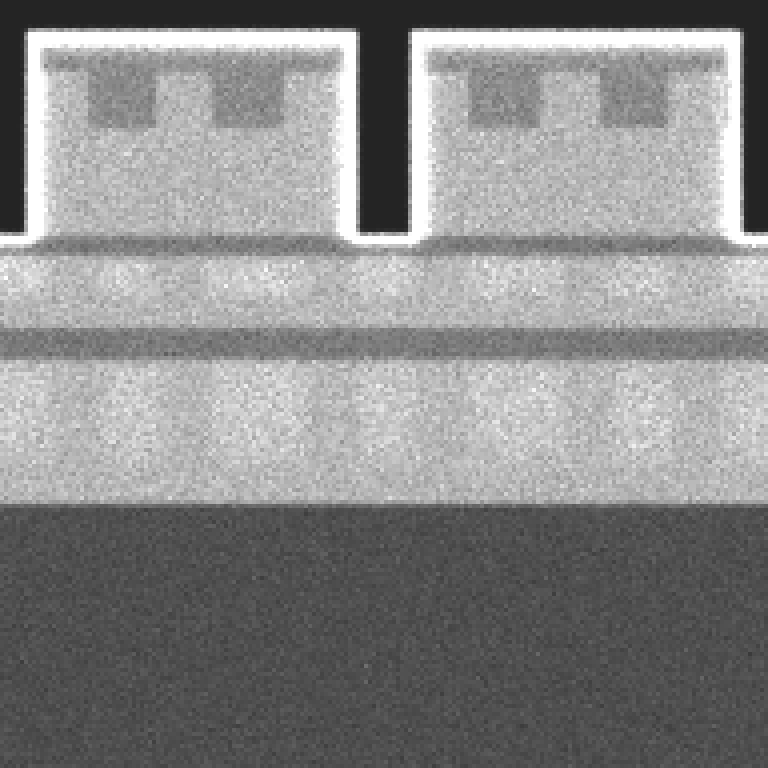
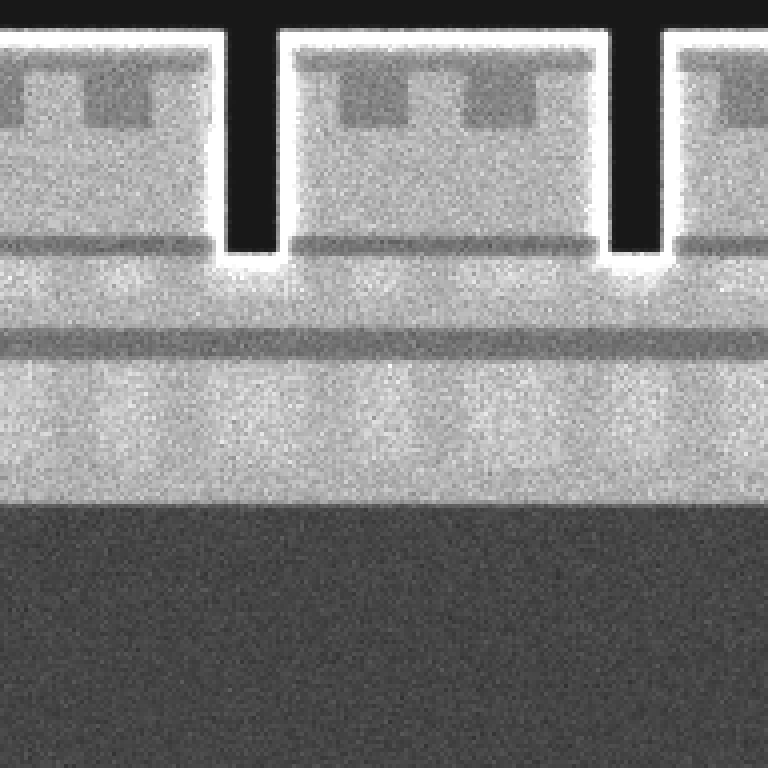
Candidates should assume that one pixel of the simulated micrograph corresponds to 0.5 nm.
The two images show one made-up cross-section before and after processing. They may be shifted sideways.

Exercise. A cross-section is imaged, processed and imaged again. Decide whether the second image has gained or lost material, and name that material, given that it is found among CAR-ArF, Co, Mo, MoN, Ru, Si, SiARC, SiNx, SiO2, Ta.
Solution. removed: SiNx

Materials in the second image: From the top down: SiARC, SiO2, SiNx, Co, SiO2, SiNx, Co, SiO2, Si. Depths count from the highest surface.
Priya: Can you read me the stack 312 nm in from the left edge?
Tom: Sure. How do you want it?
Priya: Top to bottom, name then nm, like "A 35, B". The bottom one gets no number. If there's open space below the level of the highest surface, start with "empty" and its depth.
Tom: empty 112, Co 20, SiO2 16, SiNx 16, Co 52, SiO2 20, Si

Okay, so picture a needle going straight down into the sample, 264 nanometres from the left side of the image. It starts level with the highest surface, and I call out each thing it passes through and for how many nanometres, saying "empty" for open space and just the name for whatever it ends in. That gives SiARC 48, SiO2 54, SiNx 10, Co 20, SiO2 16, SiNx 16, Co 52, SiO2 20, Si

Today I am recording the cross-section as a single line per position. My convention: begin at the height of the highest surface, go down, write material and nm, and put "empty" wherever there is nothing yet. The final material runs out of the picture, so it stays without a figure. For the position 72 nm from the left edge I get SiARC 48, SiO2 54, SiNx 10, Co 20, SiO2 16, SiNx 16, Co 52, SiO2 20, Si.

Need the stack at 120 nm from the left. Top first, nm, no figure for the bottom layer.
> empty 112, Co 20, SiO2 16, SiNx 16, Co 52, SiO2 20, Si